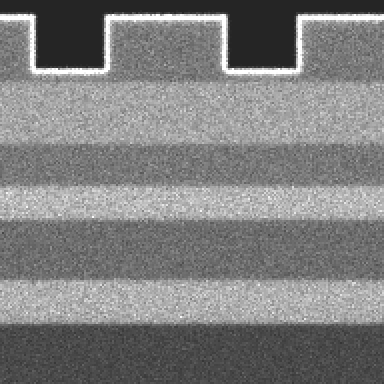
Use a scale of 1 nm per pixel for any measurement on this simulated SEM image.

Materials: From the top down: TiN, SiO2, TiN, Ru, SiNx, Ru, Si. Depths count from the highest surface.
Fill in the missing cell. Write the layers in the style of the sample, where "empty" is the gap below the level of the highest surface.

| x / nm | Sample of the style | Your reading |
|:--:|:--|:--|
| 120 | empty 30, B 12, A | TiN 66, SiO2 62, TiN 42, Ru 34, SiNx 60, Ru 44, Si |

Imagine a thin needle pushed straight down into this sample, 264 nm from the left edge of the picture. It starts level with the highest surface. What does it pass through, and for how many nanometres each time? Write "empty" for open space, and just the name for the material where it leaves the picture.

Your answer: empty 54, TiN 12, SiO2 62, TiN 42, Ru 34, SiNx 60, Ru 44, Si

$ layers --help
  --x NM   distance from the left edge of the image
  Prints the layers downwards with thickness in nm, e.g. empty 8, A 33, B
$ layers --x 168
TiN 66, SiO2 62, TiN 42, Ru 34, SiNx 60, Ru 44, Si